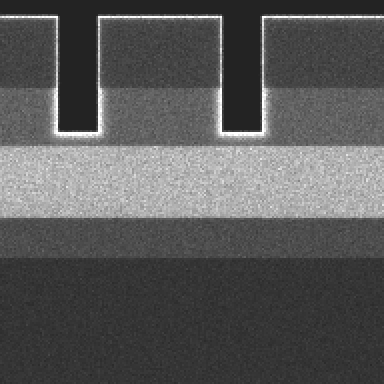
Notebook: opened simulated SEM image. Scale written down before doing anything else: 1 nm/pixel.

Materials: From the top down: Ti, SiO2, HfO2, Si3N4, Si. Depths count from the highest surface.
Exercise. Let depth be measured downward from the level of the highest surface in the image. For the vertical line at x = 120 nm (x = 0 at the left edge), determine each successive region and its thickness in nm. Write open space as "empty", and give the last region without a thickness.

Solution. Ti 72, SiO2 58, HfO2 72, Si3N4 40, Si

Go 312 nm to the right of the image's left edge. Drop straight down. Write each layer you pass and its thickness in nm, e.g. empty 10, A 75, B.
Ti 72, SiO2 58, HfO2 72, Si3N4 40, Si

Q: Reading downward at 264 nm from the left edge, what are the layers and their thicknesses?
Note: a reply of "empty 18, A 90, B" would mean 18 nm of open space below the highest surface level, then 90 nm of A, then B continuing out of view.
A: Ti 72, SiO2 58, HfO2 72, Si3N4 40, Si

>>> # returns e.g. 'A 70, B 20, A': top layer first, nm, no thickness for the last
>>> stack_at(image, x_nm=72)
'empty 116, SiO2 14, HfO2 72, Si3N4 40, Si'